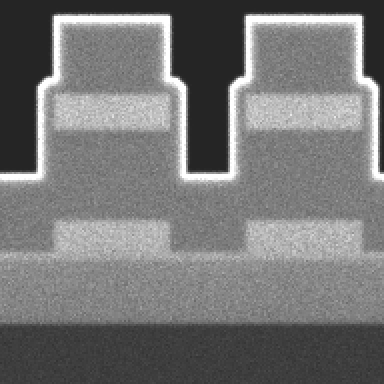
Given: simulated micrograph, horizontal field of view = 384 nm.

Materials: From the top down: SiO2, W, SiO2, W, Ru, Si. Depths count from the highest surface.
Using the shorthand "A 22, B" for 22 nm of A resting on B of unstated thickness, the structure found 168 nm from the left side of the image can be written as SiO2 78, W 36, SiO2 90, W 40, Ru 64, Si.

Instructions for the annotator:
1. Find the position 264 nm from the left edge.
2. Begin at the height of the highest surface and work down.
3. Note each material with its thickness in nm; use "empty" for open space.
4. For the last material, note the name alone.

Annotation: SiO2 78, W 36, SiO2 90, W 40, Ru 64, Si